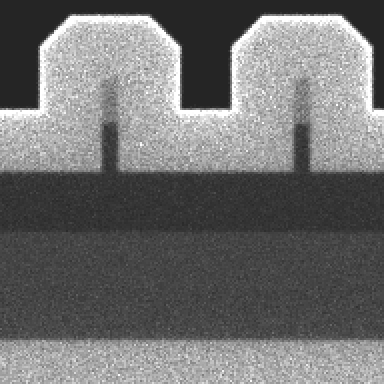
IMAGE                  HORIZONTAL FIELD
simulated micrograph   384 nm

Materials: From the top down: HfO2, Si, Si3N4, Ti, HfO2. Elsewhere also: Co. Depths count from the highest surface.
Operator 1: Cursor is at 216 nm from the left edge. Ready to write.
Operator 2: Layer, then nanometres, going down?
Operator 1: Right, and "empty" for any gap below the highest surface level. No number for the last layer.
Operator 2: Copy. empty 94, HfO2 62, Si 60, Si3N4 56, Ti 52, HfO2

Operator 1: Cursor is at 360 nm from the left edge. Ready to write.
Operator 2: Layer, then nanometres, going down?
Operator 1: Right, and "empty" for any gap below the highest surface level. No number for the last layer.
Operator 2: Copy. empty 20, HfO2 136, Si 60, Si3N4 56, Ti 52, HfO2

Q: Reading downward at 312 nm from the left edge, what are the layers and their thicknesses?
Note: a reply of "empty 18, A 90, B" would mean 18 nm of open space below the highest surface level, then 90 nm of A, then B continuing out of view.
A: HfO2 156, Si 60, Si3N4 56, Ti 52, HfO2